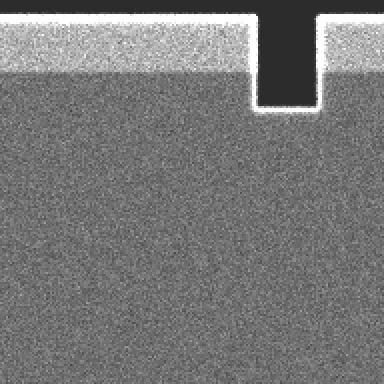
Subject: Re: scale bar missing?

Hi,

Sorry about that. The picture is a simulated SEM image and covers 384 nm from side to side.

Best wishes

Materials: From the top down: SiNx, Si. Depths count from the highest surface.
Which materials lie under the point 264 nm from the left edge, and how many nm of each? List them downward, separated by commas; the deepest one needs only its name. empty 92, Si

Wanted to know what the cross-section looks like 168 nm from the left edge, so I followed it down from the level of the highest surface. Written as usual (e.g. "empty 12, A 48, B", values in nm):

SiNx 56, Si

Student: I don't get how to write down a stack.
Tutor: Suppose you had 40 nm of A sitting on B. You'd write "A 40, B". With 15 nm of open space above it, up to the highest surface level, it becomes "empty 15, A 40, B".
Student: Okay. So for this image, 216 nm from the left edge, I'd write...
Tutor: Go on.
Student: SiNx 56, Si